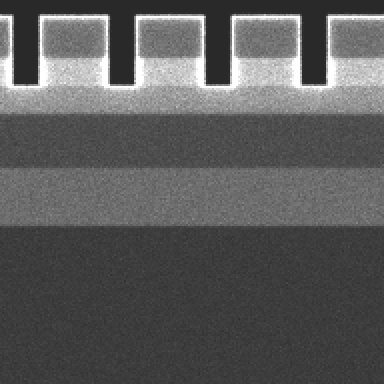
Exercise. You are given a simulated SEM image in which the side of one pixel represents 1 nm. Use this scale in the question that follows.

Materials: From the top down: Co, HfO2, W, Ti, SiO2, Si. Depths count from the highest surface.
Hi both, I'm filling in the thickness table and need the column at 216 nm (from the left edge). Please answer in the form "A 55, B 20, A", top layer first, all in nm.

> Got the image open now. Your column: empty 70, W 28, Ti 54, SiO2 58, Si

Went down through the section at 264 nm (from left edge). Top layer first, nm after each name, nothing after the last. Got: Co 42, HfO2 28, W 28, Ti 54, SiO2 58, Si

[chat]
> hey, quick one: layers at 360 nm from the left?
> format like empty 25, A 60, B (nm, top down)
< Co 42, HfO2 28, W 28, Ti 54, SiO2 58, Si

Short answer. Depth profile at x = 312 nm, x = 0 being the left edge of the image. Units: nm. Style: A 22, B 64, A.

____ empty 70, W 28, Ti 54, SiO2 58, Si